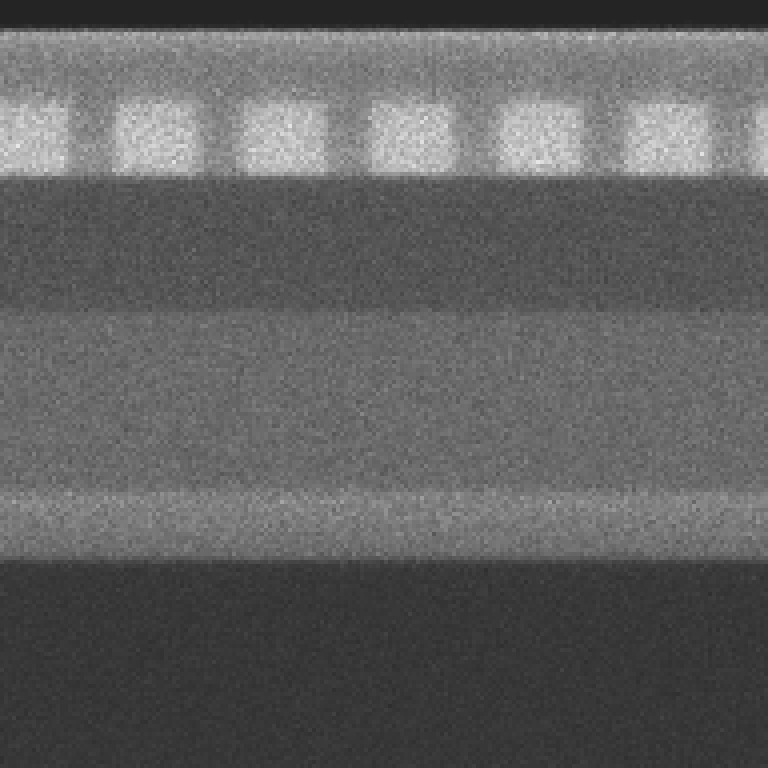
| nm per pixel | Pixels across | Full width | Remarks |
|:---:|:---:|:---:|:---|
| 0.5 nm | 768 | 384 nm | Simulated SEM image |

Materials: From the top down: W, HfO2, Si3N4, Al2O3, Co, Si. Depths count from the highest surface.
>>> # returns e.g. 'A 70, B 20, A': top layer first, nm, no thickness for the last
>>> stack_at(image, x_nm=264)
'W 36, HfO2 36, Si3N4 68, Al2O3 90, Co 34, Si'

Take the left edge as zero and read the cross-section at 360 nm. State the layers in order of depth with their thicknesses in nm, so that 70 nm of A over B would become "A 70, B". W 72, Si3N4 68, Al2O3 90, Co 34, Si